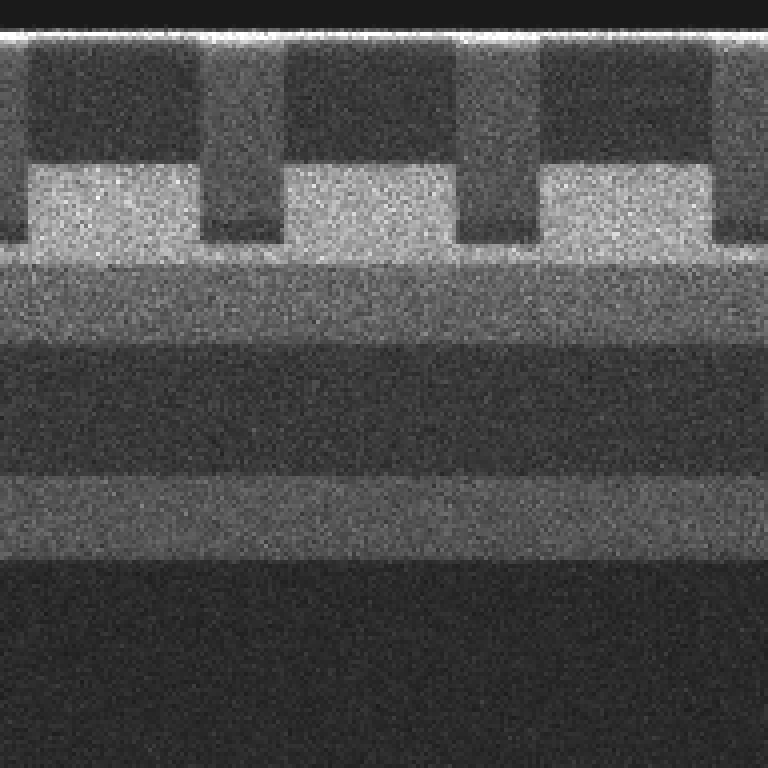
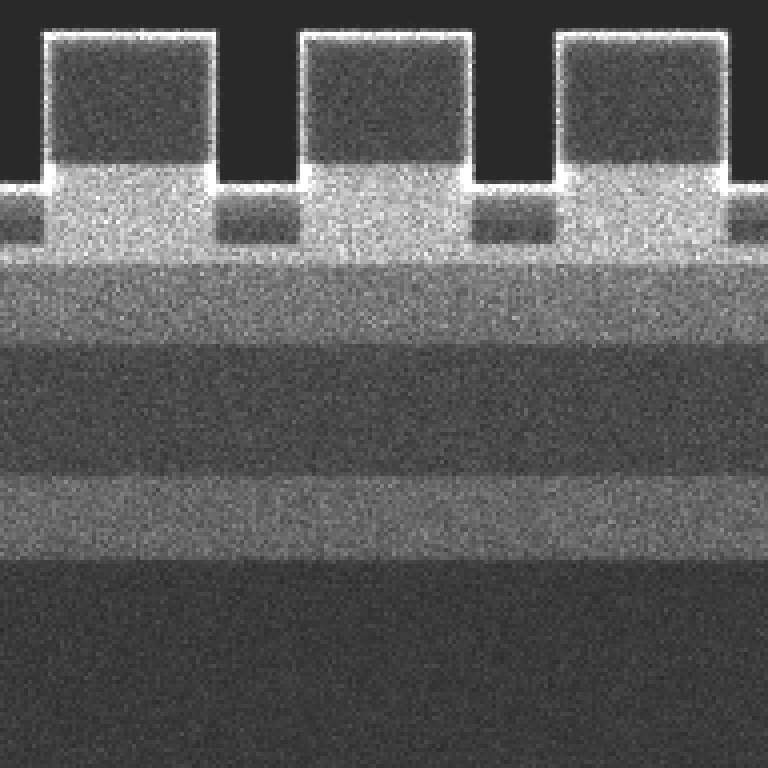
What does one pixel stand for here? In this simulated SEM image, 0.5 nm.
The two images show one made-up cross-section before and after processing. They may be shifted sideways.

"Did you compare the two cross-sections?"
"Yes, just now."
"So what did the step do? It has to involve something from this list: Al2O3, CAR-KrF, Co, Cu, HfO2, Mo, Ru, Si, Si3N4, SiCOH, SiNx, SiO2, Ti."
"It removed SiO2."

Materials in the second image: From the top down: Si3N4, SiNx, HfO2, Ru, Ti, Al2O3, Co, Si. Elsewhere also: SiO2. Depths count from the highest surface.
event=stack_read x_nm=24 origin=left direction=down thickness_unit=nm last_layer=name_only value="Si3N4 12, SiNx 54, HfO2 50, Ru 40, Ti 66, Al2O3 32, Co 10, Si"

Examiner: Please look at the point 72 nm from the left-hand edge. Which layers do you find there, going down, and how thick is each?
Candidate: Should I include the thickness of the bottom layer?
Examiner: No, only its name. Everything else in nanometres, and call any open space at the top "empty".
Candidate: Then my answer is Si3N4 12, SiNx 54, HfO2 50, Ru 40, Ti 66, Al2O3 32, Co 10, Si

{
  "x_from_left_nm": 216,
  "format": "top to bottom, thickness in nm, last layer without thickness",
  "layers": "Si3N4 12, SiNx 54, HfO2 50, Ru 40, Ti 66, Al2O3 32, Co 10, Si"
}